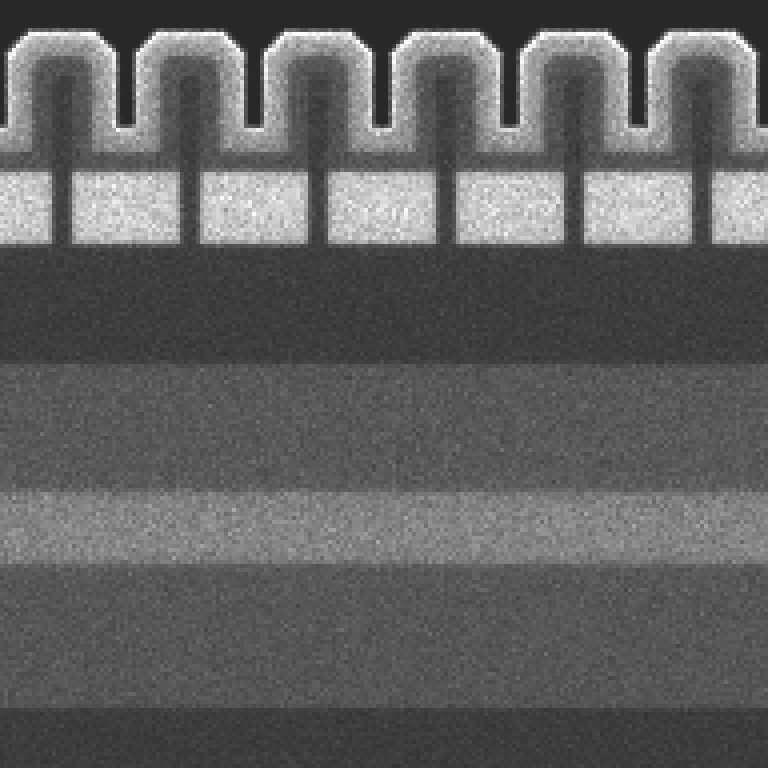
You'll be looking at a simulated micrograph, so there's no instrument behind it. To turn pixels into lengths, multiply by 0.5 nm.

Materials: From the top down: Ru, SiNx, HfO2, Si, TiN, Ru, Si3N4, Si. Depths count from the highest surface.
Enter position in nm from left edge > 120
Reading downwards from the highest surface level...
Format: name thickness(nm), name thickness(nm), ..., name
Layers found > empty 10, Ru 50, SiNx 10, HfO2 36, Si 60, TiN 64, Ru 36, Si3N4 72, Si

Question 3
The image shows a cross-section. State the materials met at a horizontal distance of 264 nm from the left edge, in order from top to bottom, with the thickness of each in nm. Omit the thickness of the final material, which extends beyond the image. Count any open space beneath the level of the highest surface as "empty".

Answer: empty 6, Ru 54, SiNx 10, HfO2 36, Si 60, TiN 64, Ru 36, Si3N4 72, Si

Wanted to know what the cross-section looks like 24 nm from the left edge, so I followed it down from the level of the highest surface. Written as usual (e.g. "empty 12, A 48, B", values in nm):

Ru 12, SiNx 58, HfO2 36, Si 60, TiN 64, Ru 36, Si3N4 72, Si